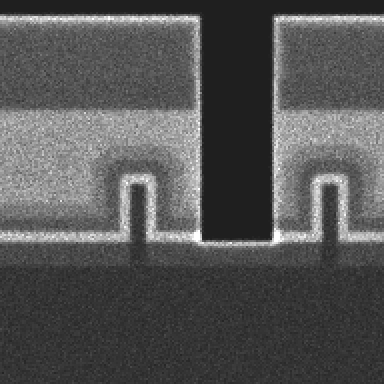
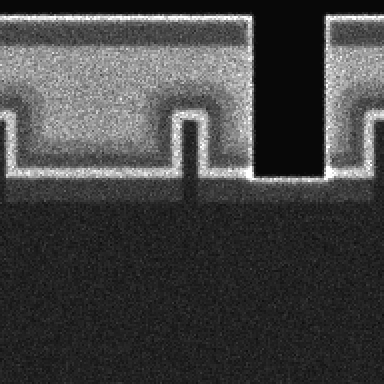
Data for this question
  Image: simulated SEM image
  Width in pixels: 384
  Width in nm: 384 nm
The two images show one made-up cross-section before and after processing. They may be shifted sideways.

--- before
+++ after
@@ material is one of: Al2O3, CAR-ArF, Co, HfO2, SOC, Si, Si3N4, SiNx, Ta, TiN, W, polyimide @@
SOC removed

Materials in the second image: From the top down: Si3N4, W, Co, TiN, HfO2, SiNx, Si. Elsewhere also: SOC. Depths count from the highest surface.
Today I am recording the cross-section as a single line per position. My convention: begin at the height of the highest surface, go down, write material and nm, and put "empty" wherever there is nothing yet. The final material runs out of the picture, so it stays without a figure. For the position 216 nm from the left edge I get Si3N4 30, W 36, Co 20, TiN 66, HfO2 10, SiNx 24, Si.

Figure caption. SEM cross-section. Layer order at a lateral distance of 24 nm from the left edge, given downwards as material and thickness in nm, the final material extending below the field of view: Si3N4 30, W 36, Co 20, TiN 66, HfO2 10, SiNx 24, Si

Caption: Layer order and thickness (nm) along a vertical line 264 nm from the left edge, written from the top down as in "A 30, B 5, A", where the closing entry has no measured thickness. empty 162, SiNx 24, Si